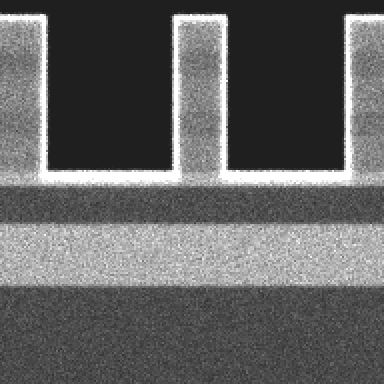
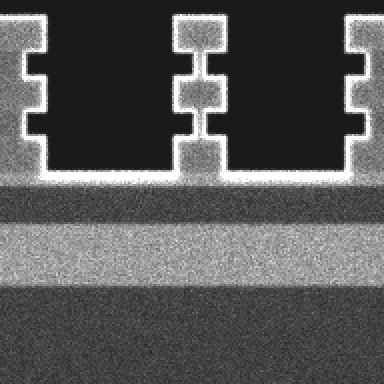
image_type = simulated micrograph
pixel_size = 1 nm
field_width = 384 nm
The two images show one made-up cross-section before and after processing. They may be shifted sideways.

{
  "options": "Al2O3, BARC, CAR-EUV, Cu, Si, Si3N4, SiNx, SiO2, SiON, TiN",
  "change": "removed",
  "material": "SiNx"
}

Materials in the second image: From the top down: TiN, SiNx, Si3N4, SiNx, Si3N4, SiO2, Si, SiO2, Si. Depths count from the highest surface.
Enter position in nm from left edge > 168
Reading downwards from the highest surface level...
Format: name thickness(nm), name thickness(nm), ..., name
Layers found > empty 156, SiO2 14, Si 38, SiO2 62, Si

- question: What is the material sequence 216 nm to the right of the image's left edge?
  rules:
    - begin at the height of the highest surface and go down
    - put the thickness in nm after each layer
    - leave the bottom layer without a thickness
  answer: TiN 36, empty 24, Si3N4 36, empty 24, Si3N4 36, SiO2 14, Si 38, SiO2 62, Si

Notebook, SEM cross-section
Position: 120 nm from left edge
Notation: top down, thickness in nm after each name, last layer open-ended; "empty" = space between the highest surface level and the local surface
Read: empty 156, SiO2 14, Si 38, SiO2 62, Si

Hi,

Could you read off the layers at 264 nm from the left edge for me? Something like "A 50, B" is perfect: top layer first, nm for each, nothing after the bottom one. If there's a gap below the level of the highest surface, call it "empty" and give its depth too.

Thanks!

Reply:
empty 156, SiO2 14, Si 38, SiO2 62, Si